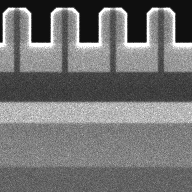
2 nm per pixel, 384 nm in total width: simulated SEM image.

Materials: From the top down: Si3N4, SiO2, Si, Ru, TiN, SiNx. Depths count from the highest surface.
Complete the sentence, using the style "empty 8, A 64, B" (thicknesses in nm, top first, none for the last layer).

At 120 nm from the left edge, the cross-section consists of Si3N4 70, SiO2 58, Si 60, Ru 42, TiN 88, SiNx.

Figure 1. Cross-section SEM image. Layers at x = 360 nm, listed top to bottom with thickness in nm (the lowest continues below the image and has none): empty 70, SiO2 58, Si 60, Ru 42, TiN 88, SiNx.